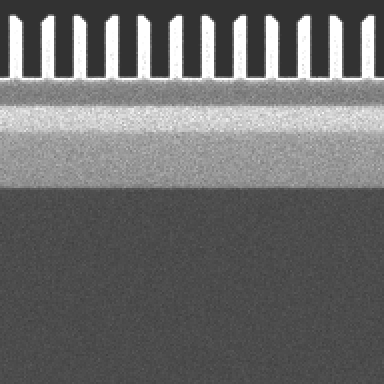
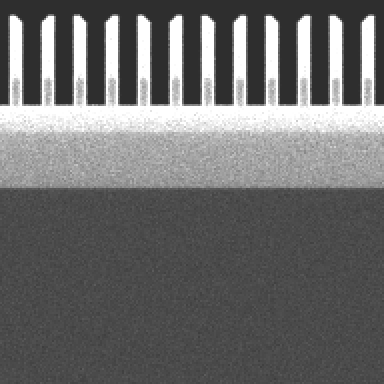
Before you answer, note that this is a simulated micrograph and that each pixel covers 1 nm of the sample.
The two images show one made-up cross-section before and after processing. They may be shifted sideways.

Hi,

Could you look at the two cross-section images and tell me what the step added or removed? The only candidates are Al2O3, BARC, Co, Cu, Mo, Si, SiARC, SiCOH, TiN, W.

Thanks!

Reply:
removed TiN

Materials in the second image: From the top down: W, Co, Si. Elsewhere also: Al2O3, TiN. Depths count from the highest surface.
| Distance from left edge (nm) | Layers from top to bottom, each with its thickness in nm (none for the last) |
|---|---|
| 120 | empty 90, W 26, Co 56, Si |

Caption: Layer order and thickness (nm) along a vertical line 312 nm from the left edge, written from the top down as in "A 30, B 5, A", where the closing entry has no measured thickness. empty 90, W 26, Co 56, Si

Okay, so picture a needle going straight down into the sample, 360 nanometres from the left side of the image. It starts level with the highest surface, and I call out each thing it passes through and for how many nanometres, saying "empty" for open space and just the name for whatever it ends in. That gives empty 90, W 26, Co 56, Si